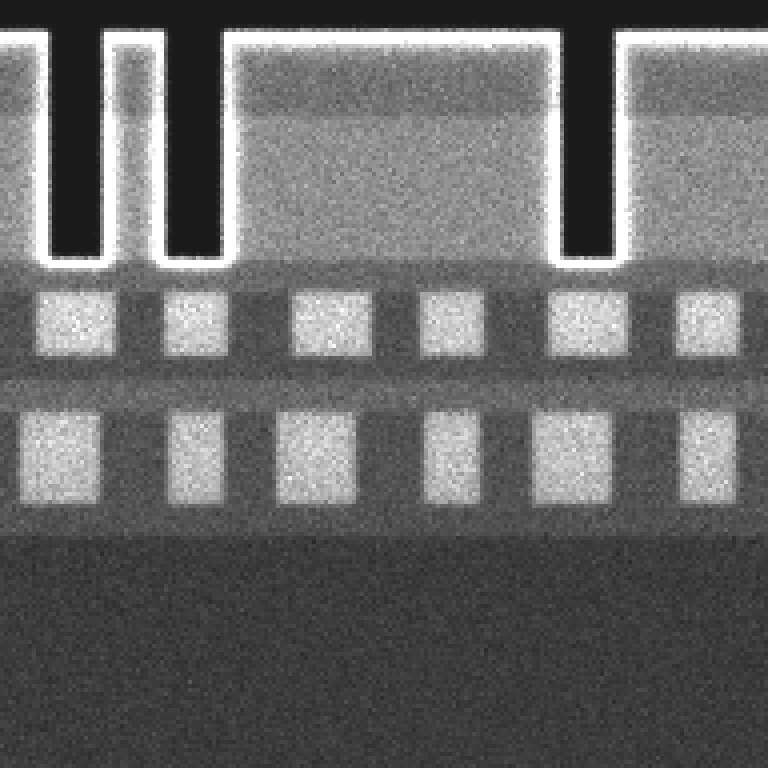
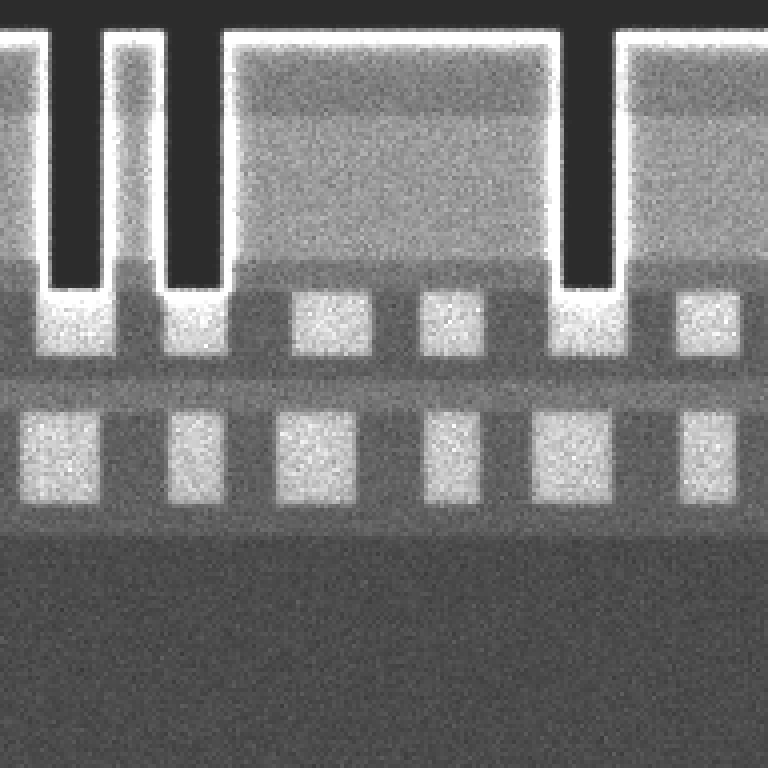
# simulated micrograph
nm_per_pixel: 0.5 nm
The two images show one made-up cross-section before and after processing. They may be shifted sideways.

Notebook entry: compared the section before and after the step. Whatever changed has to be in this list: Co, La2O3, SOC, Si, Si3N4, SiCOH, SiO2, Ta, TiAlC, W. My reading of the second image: Si3N4 removed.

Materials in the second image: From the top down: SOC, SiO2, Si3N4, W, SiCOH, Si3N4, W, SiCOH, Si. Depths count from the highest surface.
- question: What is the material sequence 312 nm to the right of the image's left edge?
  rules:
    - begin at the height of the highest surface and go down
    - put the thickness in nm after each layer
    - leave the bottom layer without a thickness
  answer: SOC 42, SiO2 72, Si3N4 16, W 32, SiCOH 12, Si3N4 16, SiCOH 62, Si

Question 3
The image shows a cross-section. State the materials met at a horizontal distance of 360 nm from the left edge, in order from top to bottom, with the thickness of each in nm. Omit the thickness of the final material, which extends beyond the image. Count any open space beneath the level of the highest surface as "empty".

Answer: SOC 42, SiO2 72, Si3N4 16, W 32, SiCOH 12, Si3N4 16, W 46, SiCOH 16, Si